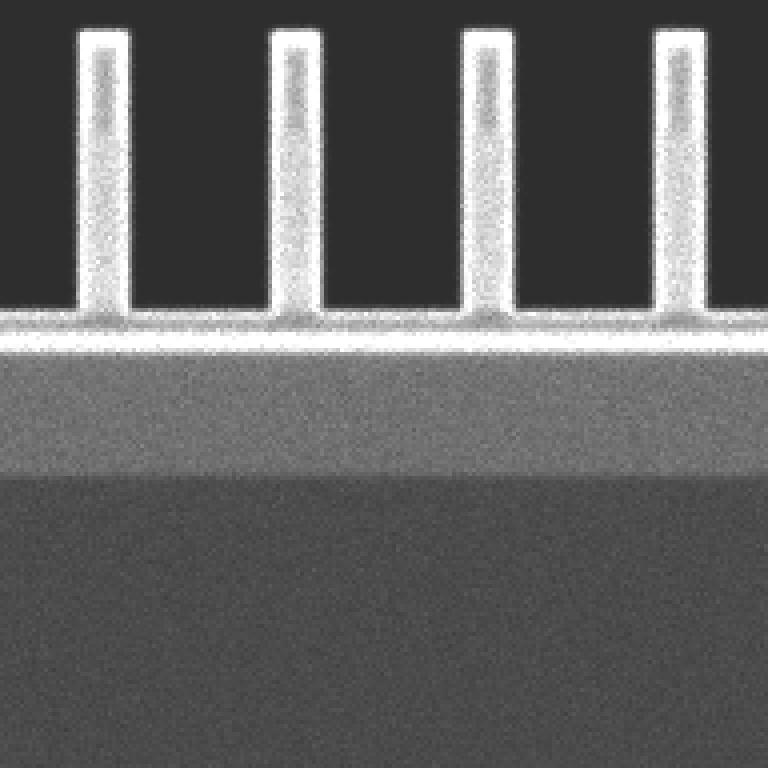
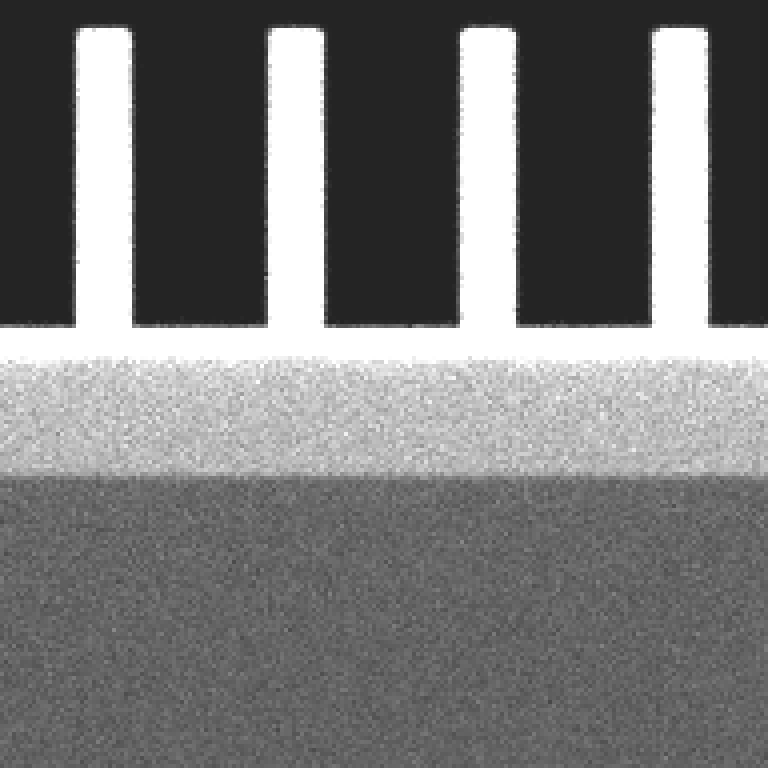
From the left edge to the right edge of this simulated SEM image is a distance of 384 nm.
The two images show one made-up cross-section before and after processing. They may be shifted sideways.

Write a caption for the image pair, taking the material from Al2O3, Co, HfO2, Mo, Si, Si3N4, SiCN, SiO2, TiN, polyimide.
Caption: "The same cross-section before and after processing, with TiN removed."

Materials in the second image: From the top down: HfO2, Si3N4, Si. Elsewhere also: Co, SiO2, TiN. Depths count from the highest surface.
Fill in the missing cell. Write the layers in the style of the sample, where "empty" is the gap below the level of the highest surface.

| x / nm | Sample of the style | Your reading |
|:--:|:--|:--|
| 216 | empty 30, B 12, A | empty 150, HfO2 10, Si3N4 62, Si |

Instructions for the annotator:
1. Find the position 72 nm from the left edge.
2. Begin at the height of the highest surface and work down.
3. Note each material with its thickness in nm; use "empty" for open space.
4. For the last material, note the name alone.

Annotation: empty 150, HfO2 10, Si3N4 62, Si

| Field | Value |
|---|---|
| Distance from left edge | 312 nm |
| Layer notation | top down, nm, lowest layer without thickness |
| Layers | empty 150, HfO2 10, Si3N4 62, Si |